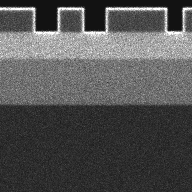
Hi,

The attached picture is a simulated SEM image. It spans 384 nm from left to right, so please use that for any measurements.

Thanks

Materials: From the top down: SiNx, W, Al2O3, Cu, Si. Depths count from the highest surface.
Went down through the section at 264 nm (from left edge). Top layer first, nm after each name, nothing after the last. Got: SiNx 48, W 54, Al2O3 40, Cu 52, Si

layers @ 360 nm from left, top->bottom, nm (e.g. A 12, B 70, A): empty 48, W 54, Al2O3 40, Cu 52, Si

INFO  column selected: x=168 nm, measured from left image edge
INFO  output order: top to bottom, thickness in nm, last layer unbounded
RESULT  empty 48, W 54, Al2O3 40, Cu 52, Si